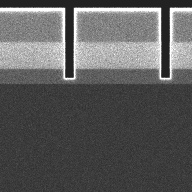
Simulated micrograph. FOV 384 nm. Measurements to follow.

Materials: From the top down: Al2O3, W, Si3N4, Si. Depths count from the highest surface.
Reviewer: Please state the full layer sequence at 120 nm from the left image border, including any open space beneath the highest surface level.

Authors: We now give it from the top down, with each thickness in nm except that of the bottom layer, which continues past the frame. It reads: Al2O3 68, W 54, Si3N4 30, Si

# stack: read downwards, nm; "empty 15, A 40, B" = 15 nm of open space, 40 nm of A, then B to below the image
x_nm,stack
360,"Al2O3 68, W 54, Si3N4 30, Si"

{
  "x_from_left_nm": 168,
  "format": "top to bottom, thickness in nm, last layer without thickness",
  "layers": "Al2O3 68, W 54, Si3N4 30, Si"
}